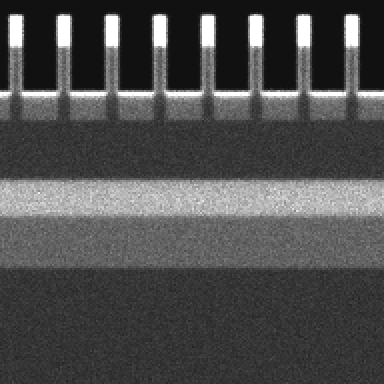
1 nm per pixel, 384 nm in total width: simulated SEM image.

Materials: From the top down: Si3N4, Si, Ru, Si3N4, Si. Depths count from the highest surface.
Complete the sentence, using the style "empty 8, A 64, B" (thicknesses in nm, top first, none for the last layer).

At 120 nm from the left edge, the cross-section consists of empty 76, Si3N4 28, Si 60, Ru 36, Si3N4 52, Si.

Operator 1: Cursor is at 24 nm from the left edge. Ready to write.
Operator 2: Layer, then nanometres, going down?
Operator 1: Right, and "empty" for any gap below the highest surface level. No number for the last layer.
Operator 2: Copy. empty 76, Si3N4 28, Si 60, Ru 36, Si3N4 52, Si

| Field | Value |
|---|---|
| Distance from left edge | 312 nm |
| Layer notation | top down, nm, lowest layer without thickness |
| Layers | empty 76, Si3N4 28, Si 60, Ru 36, Si3N4 52, Si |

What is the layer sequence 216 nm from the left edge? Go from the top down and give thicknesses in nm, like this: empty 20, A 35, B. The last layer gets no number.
empty 76, Si3N4 28, Si 60, Ru 36, Si3N4 52, Si